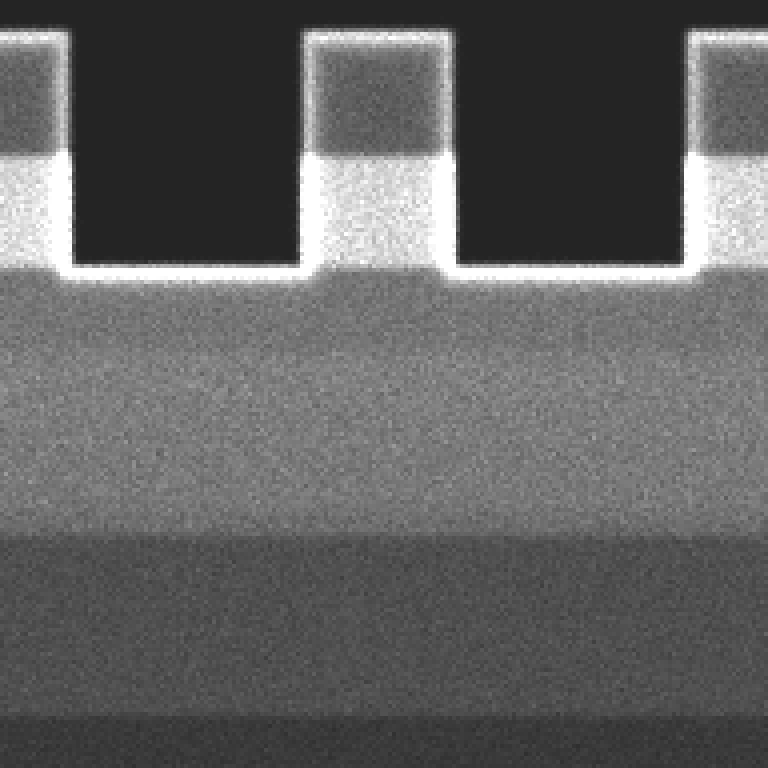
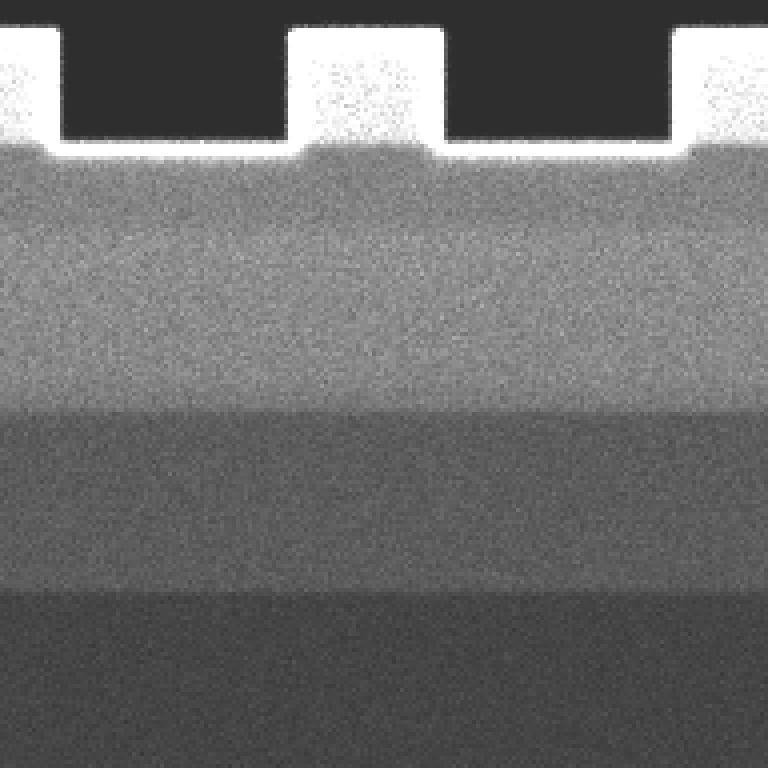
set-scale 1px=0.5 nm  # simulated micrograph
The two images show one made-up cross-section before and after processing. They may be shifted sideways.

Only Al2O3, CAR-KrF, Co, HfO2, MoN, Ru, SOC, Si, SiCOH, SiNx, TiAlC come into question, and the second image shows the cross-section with SOC removed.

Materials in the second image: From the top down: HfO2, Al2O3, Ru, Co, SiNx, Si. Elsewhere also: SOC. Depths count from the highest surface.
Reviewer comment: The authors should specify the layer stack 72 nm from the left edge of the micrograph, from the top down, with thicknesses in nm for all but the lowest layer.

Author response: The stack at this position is empty 56, Al2O3 42, Ru 80, Co 12, SiNx 90, Si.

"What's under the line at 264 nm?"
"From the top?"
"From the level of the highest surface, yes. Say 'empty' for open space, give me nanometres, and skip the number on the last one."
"empty 56, Al2O3 42, Ru 80, Co 12, SiNx 90, Si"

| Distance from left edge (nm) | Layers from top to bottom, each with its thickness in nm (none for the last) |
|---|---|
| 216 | HfO2 56, Al2O3 42, Ru 80, Co 12, SiNx 90, Si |